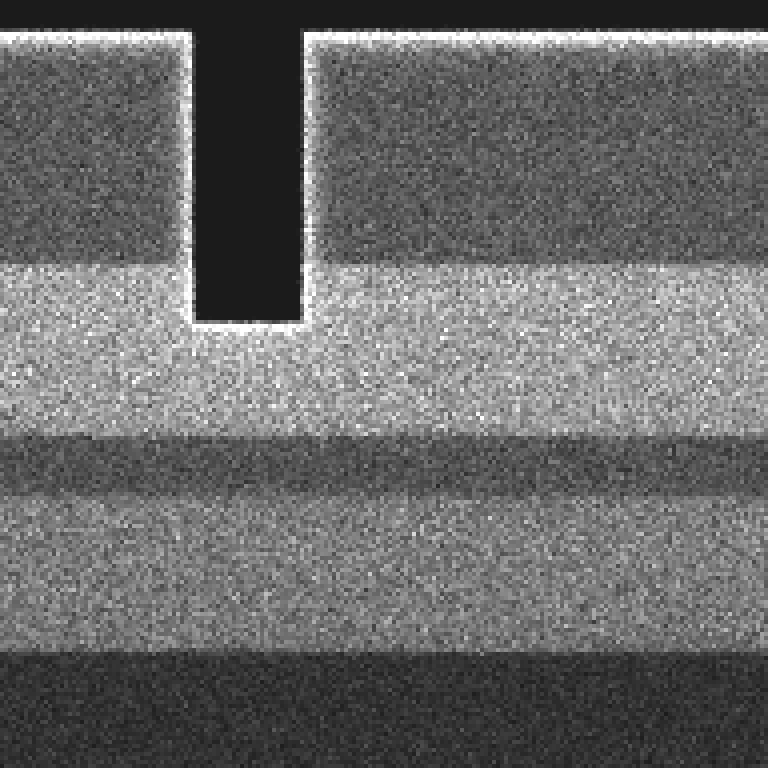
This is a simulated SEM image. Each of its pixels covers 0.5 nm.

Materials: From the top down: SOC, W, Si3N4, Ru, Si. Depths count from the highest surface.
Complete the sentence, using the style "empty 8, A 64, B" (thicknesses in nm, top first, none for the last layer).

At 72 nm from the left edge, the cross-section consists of SOC 116, W 86, Si3N4 30, Ru 78, Si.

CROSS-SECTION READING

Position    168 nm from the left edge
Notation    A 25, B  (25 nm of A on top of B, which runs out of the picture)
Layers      SOC 116, W 86, Si3N4 30, Ru 78, Si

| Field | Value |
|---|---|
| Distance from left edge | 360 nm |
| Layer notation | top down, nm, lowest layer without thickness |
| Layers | SOC 116, W 86, Si3N4 30, Ru 78, Si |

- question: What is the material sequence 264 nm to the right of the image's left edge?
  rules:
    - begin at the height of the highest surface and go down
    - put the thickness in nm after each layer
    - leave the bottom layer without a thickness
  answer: SOC 116, W 86, Si3N4 30, Ru 78, Si